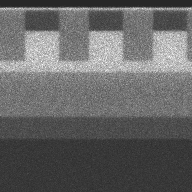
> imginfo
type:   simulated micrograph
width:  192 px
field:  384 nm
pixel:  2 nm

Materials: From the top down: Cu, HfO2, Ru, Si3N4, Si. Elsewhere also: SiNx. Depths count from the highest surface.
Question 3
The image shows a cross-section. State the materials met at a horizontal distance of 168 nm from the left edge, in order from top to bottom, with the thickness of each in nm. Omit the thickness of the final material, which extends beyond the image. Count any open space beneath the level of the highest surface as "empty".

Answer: Cu 106, HfO2 22, Ru 90, Si3N4 44, Si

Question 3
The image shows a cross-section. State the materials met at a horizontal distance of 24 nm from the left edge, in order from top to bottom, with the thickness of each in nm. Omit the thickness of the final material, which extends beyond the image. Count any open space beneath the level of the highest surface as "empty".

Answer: Cu 106, HfO2 22, Ru 90, Si3N4 44, Si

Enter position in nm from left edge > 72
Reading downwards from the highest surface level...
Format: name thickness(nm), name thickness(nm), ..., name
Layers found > SiNx 46, HfO2 82, Ru 90, Si3N4 44, Si